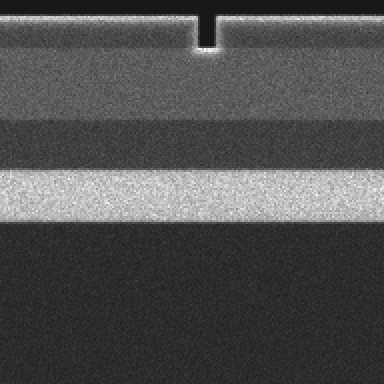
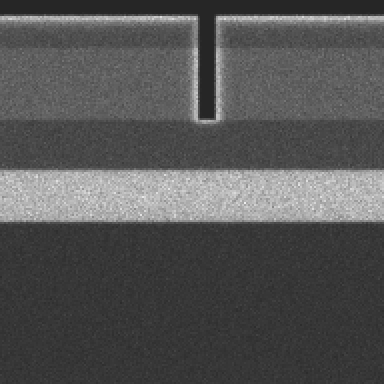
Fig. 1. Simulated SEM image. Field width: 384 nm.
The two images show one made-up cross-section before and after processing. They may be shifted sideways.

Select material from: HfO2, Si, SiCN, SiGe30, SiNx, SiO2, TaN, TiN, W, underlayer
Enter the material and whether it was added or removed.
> SiO2 / removed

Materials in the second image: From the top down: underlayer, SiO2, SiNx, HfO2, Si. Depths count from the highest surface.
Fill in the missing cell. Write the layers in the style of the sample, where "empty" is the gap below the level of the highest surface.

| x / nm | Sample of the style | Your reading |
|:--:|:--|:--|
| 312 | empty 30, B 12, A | underlayer 32, SiO2 72, SiNx 50, HfO2 52, Si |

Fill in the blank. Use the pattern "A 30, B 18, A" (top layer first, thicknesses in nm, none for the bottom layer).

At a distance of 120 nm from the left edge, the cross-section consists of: underlayer 32, SiO2 72, SiNx 50, HfO2 52, Si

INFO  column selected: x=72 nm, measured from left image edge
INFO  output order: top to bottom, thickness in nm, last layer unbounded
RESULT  underlayer 32, SiO2 72, SiNx 50, HfO2 52, Si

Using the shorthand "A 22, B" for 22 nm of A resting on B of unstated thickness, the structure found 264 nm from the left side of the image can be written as underlayer 32, SiO2 72, SiNx 50, HfO2 52, Si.